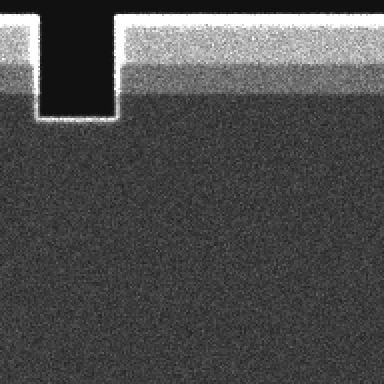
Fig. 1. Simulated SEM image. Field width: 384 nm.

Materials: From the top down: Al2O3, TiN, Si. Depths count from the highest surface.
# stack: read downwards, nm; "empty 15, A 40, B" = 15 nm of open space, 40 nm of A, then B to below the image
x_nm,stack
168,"Al2O3 48, TiN 30, Si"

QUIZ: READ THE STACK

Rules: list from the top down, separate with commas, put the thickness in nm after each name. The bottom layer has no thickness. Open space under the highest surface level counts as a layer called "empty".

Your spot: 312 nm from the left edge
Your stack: Al2O3 48, TiN 30, Si